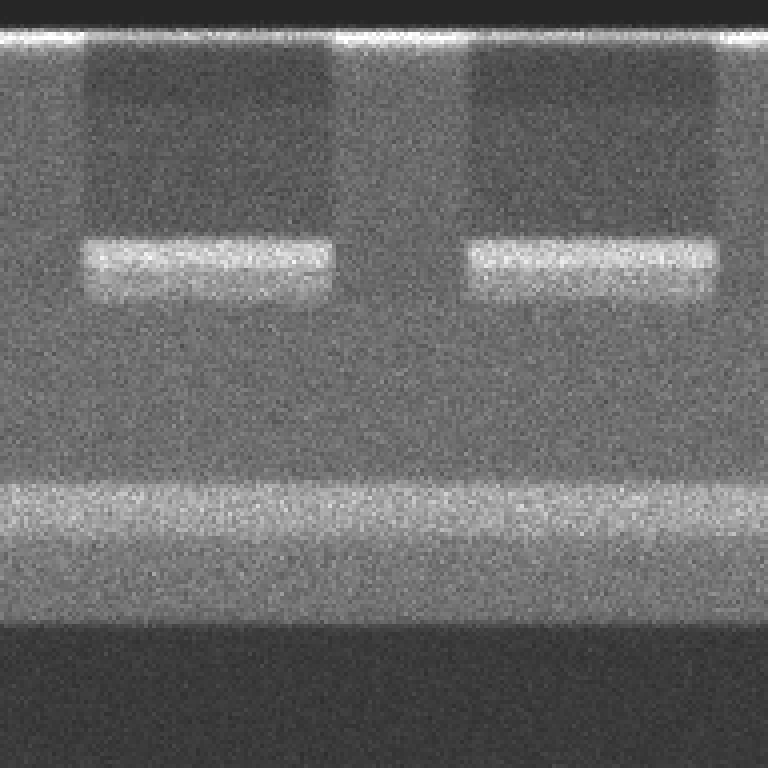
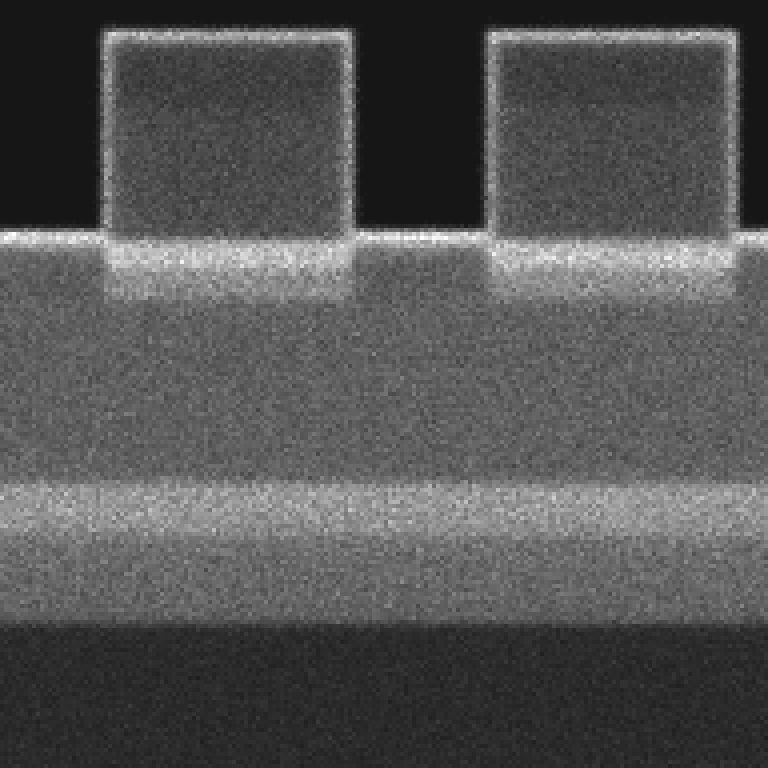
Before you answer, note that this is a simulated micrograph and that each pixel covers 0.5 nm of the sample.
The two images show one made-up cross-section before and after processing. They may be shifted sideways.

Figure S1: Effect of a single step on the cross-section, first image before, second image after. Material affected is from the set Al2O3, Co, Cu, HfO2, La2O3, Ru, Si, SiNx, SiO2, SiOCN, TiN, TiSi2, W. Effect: removed SiO2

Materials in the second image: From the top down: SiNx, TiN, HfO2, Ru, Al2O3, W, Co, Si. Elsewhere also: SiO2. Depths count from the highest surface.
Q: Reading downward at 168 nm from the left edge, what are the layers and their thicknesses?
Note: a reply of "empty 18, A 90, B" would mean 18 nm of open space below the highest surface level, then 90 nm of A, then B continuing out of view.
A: SiNx 36, TiN 68, HfO2 14, Ru 16, Al2O3 92, W 26, Co 44, Si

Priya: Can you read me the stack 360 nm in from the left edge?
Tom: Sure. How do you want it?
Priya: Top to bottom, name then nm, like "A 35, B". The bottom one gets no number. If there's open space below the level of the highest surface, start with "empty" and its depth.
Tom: SiNx 36, TiN 68, HfO2 14, Ru 16, Al2O3 92, W 26, Co 44, Si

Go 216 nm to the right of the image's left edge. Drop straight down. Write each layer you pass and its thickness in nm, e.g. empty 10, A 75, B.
empty 100, SiO2 34, Al2O3 92, W 26, Co 44, Si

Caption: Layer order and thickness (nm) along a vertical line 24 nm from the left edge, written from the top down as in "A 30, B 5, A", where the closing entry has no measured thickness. empty 100, SiO2 34, Al2O3 92, W 26, Co 44, Si